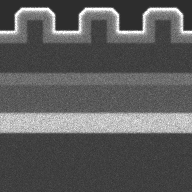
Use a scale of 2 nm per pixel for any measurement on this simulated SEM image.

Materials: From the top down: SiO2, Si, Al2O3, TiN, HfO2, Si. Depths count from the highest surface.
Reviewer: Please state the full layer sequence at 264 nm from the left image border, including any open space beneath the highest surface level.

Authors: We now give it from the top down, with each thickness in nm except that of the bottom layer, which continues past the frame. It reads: empty 46, SiO2 24, Si 60, Al2O3 24, TiN 56, HfO2 40, Si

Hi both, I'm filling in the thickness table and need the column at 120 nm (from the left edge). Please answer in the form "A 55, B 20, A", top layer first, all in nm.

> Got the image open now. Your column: empty 46, SiO2 24, Si 60, Al2O3 24, TiN 56, HfO2 40, Si